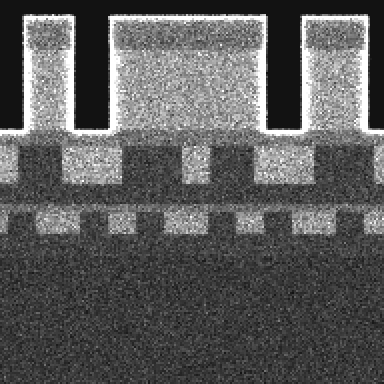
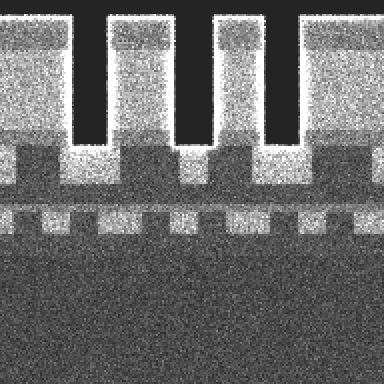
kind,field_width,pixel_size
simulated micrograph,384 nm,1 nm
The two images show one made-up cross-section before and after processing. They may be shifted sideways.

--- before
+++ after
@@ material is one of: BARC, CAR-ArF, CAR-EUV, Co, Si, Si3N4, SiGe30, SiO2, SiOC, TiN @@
Si3N4 removed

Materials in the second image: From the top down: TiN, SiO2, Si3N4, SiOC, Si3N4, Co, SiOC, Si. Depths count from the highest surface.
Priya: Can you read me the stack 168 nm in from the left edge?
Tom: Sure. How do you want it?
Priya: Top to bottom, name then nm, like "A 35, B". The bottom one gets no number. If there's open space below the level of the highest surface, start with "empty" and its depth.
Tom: TiN 34, SiO2 80, Si3N4 16, SiOC 58, Si3N4 8, SiOC 44, Si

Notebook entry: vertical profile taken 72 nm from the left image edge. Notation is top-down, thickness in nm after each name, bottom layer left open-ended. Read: empty 130, Co 38, SiOC 20, Si3N4 8, SiOC 44, Si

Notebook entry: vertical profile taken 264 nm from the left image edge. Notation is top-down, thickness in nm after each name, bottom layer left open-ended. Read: empty 130, Co 38, SiOC 20, Si3N4 8, Co 22, SiOC 22, Si